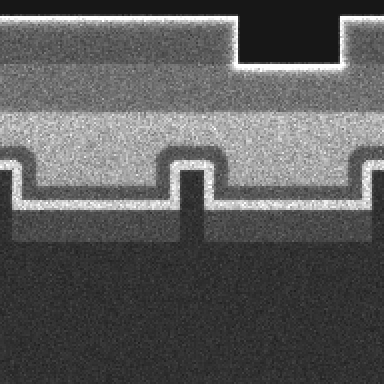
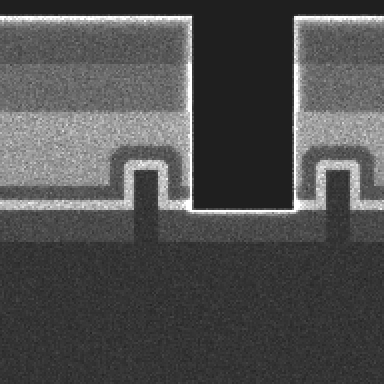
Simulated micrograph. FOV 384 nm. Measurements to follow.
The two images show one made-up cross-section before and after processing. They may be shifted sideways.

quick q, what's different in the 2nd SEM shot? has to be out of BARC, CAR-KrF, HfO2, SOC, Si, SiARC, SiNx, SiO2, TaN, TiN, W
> HfO2 and SiO2 and TiN and W removed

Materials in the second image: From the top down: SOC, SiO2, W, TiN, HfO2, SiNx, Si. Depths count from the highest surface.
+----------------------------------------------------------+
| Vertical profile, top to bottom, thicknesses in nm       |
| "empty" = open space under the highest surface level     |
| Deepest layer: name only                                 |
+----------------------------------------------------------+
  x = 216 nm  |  empty 194, SiNx 32, Si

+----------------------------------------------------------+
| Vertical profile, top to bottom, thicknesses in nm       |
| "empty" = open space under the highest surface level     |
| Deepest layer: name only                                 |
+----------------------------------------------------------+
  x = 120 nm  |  SOC 48, SiO2 48, W 34, TiN 54, HfO2 10, SiNx 32, Si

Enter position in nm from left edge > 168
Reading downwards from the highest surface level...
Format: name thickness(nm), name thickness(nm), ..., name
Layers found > SOC 48, SiO2 48, W 34, TiN 54, HfO2 10, SiNx 32, Si